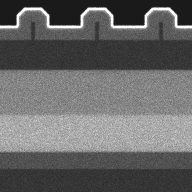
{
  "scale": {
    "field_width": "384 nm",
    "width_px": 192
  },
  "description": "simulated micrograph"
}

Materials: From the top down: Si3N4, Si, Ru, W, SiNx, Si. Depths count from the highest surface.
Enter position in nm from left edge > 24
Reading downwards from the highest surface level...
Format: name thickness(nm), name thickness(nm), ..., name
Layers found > empty 36, Si3N4 28, Si 60, Ru 90, W 74, SiNx 34, Si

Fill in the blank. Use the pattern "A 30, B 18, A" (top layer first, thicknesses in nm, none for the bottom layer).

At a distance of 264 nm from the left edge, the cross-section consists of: empty 36, Si3N4 28, Si 60, Ru 90, W 74, SiNx 34, Si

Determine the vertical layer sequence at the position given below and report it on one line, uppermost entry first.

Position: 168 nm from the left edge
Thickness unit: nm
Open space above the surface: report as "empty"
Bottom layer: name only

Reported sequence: empty 8, Si3N4 56, Si 60, Ru 90, W 74, SiNx 34, Si